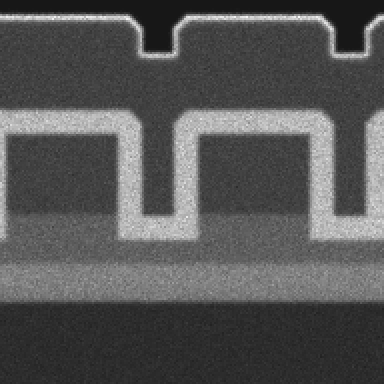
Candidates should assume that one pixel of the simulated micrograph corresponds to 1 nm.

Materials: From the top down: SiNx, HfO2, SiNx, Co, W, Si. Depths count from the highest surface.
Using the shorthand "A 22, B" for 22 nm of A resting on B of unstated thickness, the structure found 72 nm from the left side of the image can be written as SiNx 94, HfO2 24, SiNx 80, Co 50, W 38, Si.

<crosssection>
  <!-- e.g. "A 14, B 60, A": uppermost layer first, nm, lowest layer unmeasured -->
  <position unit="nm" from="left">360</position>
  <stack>empty 38, SiNx 162, HfO2 24, Co 24, W 38, Si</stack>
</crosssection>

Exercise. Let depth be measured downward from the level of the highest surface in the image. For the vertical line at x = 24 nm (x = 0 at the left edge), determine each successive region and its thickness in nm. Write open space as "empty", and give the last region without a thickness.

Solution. SiNx 94, HfO2 24, SiNx 80, Co 50, W 38, Si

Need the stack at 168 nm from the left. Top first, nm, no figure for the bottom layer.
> empty 38, SiNx 162, HfO2 24, Co 24, W 38, Si